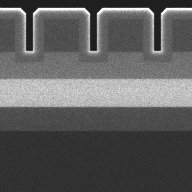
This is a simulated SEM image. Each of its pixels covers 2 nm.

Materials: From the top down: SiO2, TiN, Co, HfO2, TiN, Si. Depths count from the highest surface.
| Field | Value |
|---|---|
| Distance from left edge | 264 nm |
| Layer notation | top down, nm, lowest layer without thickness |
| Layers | SiO2 22, TiN 66, Co 54, HfO2 56, TiN 48, Si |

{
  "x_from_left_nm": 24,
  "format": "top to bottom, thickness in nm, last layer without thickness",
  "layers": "SiO2 22, TiN 66, Co 54, HfO2 56, TiN 48, Si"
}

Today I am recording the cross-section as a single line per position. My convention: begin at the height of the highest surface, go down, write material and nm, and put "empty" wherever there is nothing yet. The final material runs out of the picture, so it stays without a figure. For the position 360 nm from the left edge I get SiO2 22, TiN 66, Co 54, HfO2 56, TiN 48, Si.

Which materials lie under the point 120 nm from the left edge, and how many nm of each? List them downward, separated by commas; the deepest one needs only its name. SiO2 22, TiN 66, Co 54, HfO2 56, TiN 48, Si